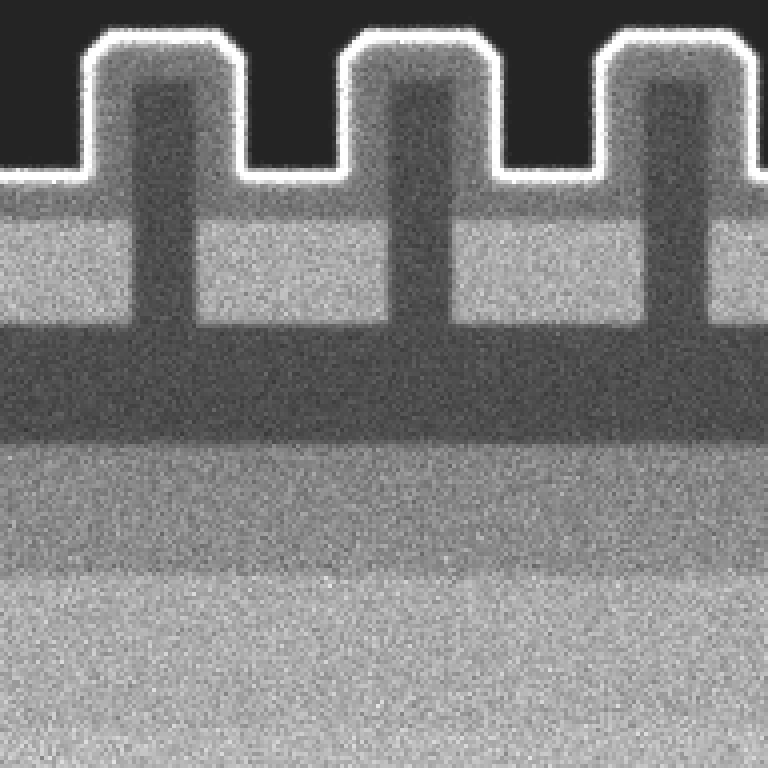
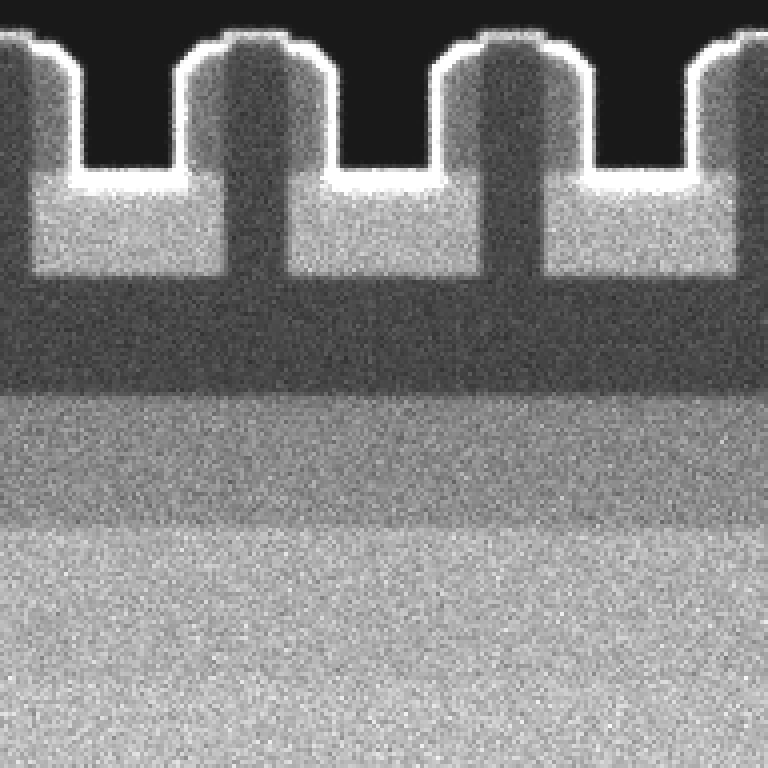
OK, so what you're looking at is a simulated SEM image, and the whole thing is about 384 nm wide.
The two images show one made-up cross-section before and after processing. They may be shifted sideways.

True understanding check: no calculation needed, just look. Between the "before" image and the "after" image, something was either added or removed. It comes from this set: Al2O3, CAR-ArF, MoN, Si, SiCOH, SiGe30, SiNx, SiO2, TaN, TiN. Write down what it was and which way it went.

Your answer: SiNx (removed)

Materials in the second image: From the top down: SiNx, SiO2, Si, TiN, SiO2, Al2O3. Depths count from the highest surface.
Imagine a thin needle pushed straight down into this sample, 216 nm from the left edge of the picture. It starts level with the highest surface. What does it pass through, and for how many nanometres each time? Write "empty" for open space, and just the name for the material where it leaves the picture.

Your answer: empty 18, SiNx 52, SiO2 52, Si 60, TiN 66, SiO2 76, Al2O3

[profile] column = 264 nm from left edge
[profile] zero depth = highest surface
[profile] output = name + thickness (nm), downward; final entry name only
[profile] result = Si 182, TiN 66, SiO2 76, Al2O3